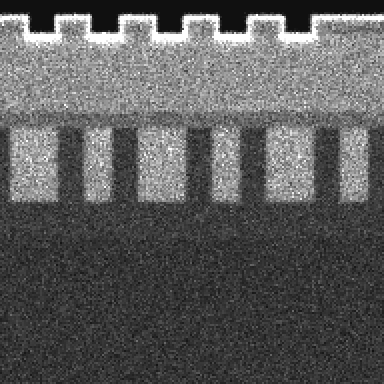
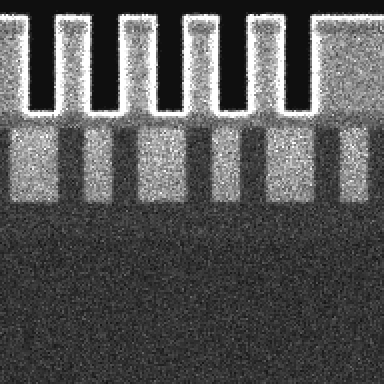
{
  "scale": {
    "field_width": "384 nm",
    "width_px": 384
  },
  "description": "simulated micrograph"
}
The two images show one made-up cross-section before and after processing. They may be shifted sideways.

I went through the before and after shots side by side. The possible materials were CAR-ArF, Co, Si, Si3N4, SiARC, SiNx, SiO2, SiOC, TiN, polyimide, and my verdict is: removed, SiO2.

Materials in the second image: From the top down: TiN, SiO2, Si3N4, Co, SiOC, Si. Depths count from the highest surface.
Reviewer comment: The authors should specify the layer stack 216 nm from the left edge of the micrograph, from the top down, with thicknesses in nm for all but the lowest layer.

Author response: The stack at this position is TiN 18, SiO2 78, Si3N4 16, Co 74, SiOC 36, Si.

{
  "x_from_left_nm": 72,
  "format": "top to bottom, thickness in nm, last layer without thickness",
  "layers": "TiN 18, SiO2 78, Si3N4 16, SiOC 110, Si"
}